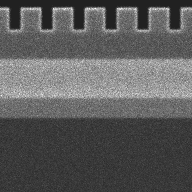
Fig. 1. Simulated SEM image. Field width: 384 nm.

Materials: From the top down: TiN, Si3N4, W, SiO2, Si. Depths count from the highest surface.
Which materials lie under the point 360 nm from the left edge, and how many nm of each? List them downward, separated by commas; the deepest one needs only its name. empty 44, TiN 6, Si3N4 52, W 78, SiO2 40, Si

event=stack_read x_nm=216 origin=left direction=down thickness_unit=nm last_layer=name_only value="empty 44, TiN 6, Si3N4 52, W 78, SiO2 40, Si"